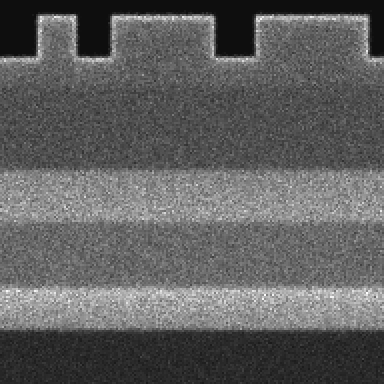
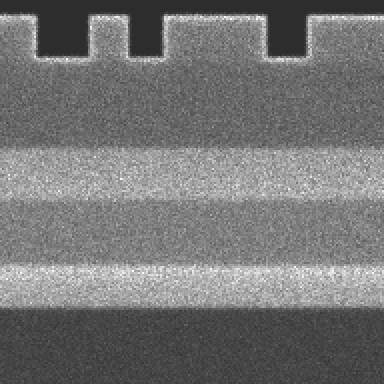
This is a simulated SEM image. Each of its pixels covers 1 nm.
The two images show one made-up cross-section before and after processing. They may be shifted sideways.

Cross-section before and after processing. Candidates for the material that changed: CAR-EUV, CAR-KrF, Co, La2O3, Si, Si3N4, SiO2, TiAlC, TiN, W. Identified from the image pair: TiN (removed).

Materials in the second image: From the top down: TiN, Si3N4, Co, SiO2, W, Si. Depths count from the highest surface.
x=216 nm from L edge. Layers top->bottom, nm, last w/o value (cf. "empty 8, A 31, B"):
TiN 48, Si3N4 84, Co 52, SiO2 66, W 42, Si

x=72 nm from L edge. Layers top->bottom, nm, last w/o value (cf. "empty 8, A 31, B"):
empty 42, TiN 6, Si3N4 84, Co 52, SiO2 66, W 42, Si